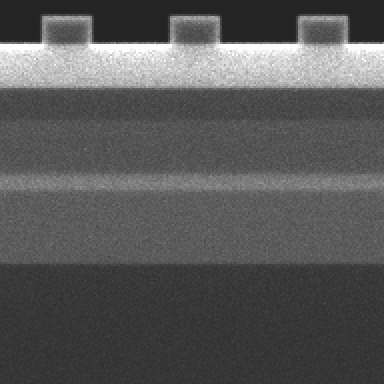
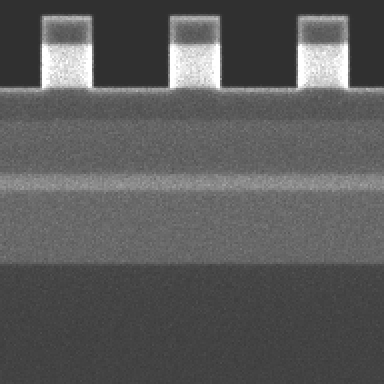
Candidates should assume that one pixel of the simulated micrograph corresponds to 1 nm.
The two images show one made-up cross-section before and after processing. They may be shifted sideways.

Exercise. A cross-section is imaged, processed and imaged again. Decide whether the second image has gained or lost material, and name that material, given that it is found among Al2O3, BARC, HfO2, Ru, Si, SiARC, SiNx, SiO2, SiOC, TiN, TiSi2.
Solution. removed: HfO2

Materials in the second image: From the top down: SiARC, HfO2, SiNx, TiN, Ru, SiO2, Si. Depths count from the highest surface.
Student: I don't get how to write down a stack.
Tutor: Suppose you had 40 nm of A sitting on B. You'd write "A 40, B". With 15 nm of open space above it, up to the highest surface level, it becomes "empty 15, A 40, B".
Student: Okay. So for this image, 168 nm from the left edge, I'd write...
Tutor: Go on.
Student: empty 72, SiNx 32, TiN 54, Ru 16, SiO2 74, Si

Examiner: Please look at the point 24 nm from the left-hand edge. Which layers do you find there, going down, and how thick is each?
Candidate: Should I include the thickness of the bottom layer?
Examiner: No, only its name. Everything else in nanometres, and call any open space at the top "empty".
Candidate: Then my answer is empty 72, SiNx 32, TiN 54, Ru 16, SiO2 74, Si